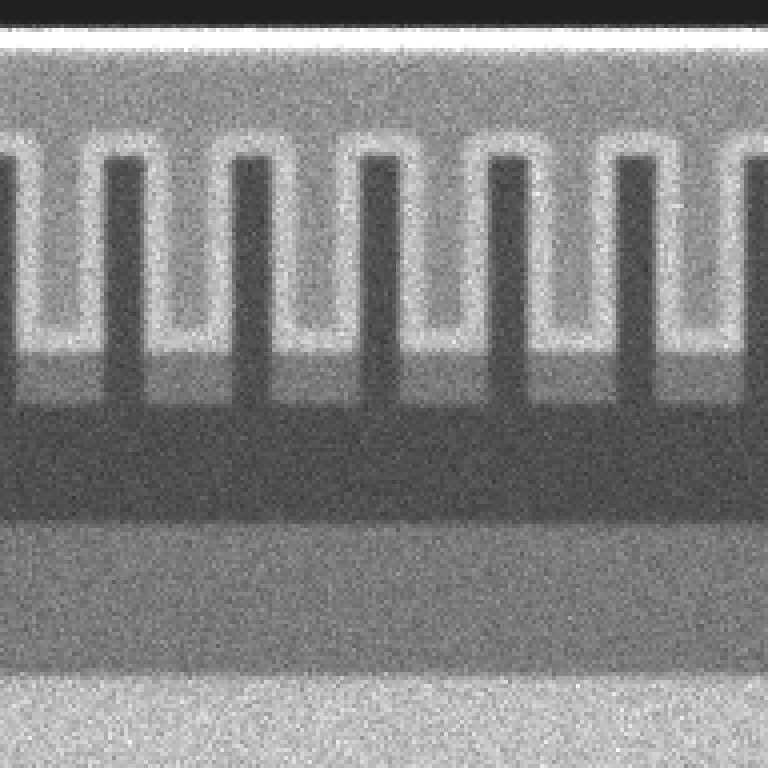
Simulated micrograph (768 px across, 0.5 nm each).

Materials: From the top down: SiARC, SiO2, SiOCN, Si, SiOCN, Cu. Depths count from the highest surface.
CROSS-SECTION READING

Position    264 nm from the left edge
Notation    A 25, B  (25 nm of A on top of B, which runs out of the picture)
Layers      SiARC 50, SiO2 110, SiOCN 26, Si 60, SiOCN 76, Cu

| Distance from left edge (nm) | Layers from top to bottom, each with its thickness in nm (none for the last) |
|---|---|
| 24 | SiARC 148, SiO2 12, SiOCN 26, Si 60, SiOCN 76, Cu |